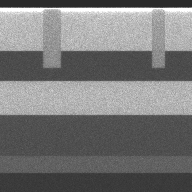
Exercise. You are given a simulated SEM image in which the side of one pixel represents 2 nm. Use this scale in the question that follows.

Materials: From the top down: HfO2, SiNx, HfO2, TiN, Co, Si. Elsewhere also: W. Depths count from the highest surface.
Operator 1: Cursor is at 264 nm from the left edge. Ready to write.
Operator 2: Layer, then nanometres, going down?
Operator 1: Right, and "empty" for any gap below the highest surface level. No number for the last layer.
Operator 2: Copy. HfO2 86, SiNx 60, HfO2 68, TiN 82, Co 34, Si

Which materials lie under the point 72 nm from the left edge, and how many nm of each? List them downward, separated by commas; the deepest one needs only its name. HfO2 86, SiNx 60, HfO2 68, TiN 82, Co 34, Si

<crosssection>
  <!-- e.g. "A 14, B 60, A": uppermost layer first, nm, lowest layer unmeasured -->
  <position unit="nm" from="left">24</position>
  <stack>HfO2 86, SiNx 60, HfO2 68, TiN 82, Co 34, Si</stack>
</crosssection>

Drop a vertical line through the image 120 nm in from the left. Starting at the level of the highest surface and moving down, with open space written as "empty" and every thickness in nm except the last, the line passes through W 120, SiNx 26, HfO2 68, TiN 82, Co 34, Si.